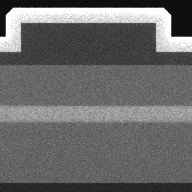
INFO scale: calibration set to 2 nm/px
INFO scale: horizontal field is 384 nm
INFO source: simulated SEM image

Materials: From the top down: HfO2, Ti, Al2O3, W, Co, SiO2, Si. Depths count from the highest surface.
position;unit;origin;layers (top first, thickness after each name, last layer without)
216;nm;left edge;HfO2 30, Ti 84, Al2O3 82, W 32, Co 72, SiO2 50, Si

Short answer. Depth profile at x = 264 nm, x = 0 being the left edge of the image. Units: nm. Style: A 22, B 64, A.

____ HfO2 30, Ti 84, Al2O3 82, W 32, Co 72, SiO2 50, Si